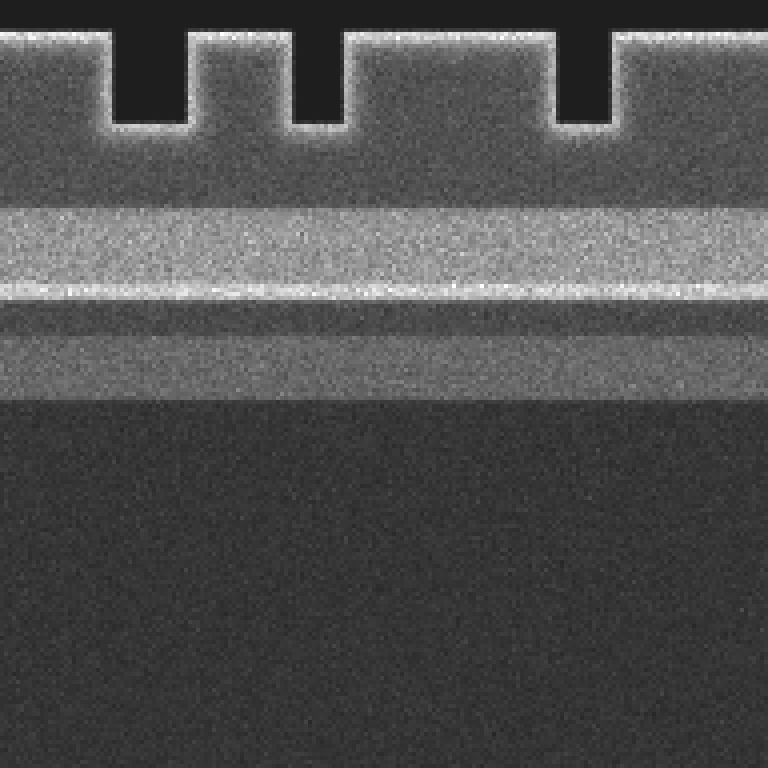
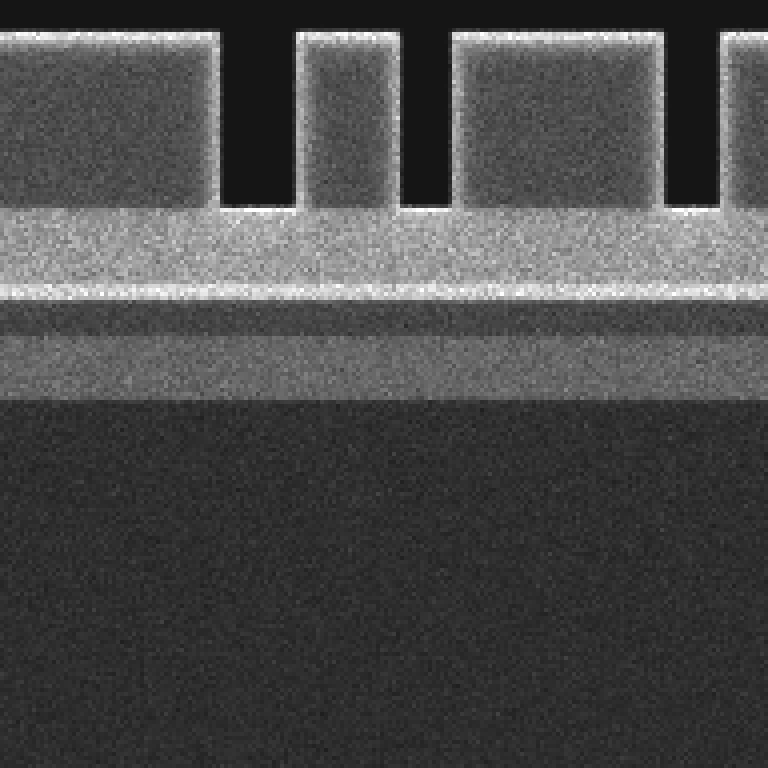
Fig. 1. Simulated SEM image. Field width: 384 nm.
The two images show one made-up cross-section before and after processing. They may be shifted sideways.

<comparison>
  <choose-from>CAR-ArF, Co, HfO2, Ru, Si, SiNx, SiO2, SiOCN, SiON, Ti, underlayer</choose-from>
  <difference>underlayer removed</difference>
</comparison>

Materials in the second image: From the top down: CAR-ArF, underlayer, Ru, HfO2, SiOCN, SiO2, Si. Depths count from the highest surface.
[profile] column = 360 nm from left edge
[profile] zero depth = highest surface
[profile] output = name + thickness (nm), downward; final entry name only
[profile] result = CAR-ArF 46, underlayer 42, Ru 38, HfO2 8, SiOCN 18, SiO2 32, Si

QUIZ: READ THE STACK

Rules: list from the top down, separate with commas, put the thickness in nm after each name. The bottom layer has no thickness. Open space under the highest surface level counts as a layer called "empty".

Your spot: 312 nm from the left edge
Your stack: CAR-ArF 46, underlayer 42, Ru 38, HfO2 8, SiOCN 18, SiO2 32, Si